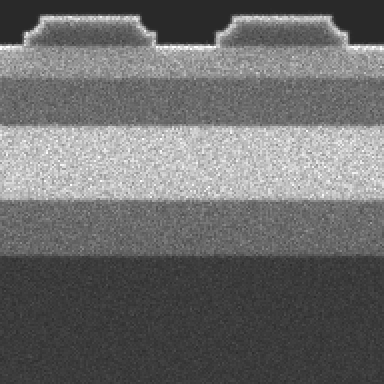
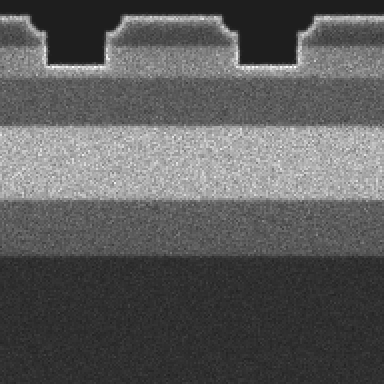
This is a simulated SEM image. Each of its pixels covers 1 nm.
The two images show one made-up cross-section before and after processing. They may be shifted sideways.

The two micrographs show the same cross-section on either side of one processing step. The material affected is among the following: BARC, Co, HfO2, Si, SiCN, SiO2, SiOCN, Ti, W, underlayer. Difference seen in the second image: W removed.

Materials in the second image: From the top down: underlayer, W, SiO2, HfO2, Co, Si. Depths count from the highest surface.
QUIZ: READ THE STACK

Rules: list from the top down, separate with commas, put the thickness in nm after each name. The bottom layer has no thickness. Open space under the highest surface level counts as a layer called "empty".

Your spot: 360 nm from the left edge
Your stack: underlayer 30, W 32, SiO2 48, HfO2 74, Co 56, Si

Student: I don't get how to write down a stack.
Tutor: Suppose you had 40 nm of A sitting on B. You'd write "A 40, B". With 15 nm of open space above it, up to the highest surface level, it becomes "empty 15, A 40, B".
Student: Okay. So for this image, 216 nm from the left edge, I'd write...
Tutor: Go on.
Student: underlayer 30, W 32, SiO2 48, HfO2 74, Co 56, Si